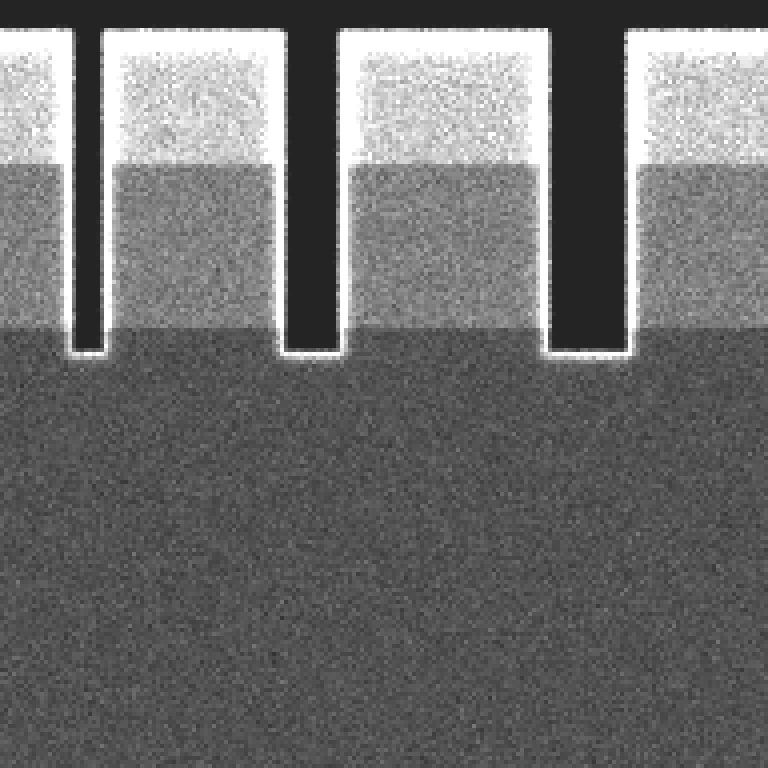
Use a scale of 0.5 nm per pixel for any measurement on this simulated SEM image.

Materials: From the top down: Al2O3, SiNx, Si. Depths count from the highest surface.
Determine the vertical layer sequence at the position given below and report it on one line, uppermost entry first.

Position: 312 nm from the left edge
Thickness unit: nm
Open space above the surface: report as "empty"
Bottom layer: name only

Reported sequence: empty 160, Si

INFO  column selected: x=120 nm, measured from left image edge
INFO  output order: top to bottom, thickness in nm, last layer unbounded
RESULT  Al2O3 66, SiNx 82, Si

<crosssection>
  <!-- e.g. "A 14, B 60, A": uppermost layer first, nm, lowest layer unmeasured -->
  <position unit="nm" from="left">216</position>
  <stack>Al2O3 66, SiNx 82, Si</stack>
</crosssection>